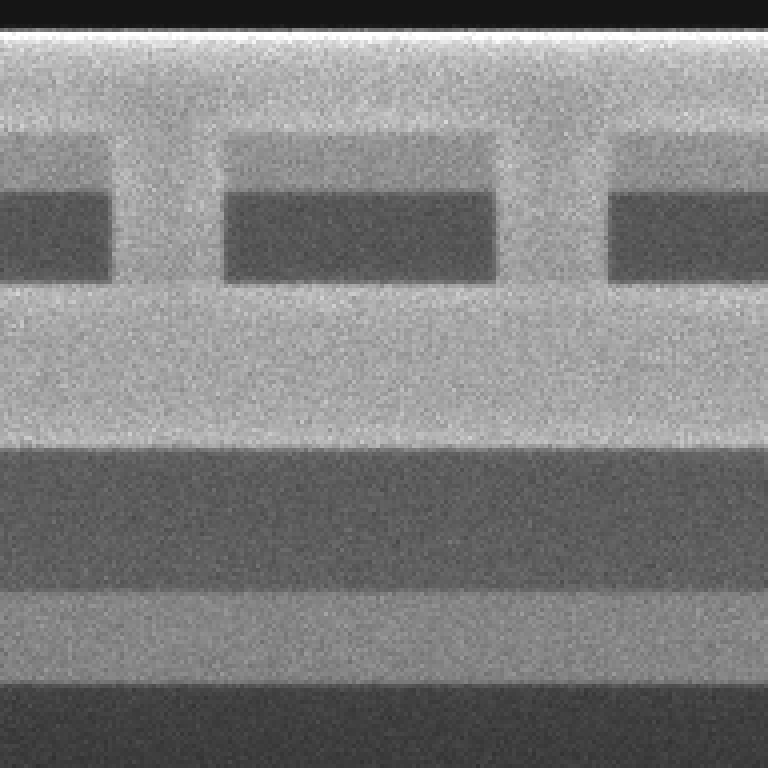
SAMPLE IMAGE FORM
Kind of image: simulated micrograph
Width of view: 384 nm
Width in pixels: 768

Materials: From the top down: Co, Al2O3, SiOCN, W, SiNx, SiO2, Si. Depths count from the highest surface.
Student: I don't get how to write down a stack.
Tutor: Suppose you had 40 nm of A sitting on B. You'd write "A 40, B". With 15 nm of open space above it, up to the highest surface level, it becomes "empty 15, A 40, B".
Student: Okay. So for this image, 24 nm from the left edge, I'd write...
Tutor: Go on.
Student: Co 50, Al2O3 30, SiOCN 46, W 82, SiNx 72, SiO2 46, Si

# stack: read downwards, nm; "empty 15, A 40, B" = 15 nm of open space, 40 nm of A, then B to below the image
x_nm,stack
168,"Co 50, Al2O3 30, SiOCN 46, W 82, SiNx 72, SiO2 46, Si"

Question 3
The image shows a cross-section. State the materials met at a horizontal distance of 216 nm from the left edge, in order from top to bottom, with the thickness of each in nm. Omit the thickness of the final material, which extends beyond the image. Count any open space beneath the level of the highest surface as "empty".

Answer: Co 50, Al2O3 30, SiOCN 46, W 82, SiNx 72, SiO2 46, Si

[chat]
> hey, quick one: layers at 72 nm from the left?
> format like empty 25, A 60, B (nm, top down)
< Co 126, W 82, SiNx 72, SiO2 46, Si